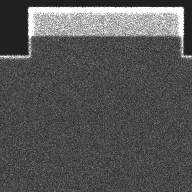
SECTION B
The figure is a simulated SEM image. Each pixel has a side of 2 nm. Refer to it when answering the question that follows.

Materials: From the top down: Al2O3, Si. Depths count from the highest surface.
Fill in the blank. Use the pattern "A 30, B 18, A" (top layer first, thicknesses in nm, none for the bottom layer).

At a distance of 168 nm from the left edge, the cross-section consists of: Al2O3 56, Si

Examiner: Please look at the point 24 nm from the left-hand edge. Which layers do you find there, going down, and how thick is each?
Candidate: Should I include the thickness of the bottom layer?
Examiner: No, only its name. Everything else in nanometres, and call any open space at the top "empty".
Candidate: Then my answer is empty 96, Si